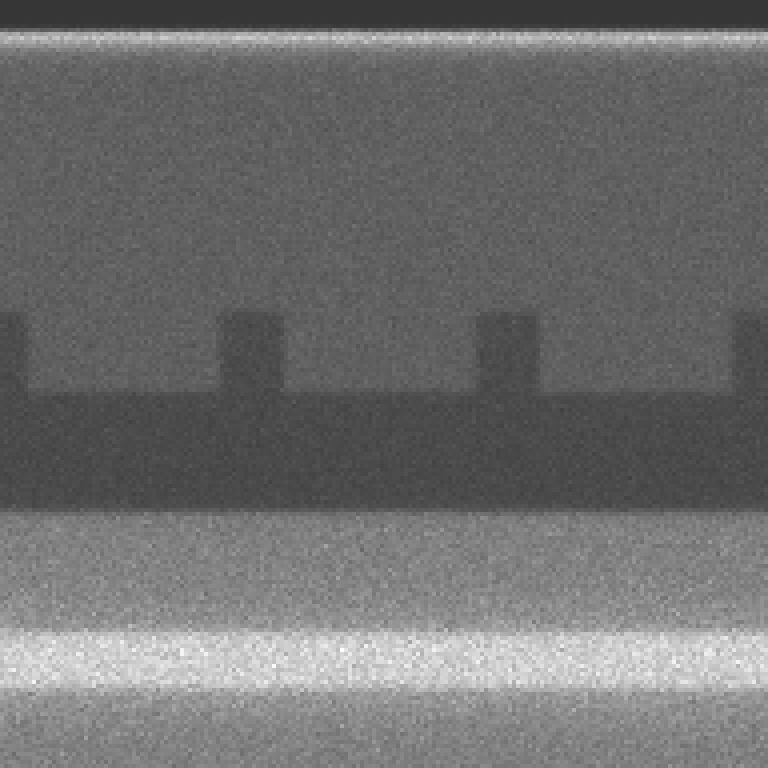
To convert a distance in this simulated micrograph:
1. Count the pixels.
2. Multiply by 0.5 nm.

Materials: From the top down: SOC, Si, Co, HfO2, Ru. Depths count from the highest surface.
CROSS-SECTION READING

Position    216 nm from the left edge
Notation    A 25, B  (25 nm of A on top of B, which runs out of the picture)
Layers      SOC 180, Si 60, Co 60, HfO2 28, Ru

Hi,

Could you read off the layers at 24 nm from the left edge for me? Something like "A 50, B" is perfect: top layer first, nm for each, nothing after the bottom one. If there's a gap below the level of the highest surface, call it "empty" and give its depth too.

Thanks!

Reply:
SOC 180, Si 60, Co 60, HfO2 28, Ru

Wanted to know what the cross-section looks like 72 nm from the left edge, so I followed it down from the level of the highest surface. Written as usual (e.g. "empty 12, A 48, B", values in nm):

SOC 180, Si 60, Co 60, HfO2 28, Ru